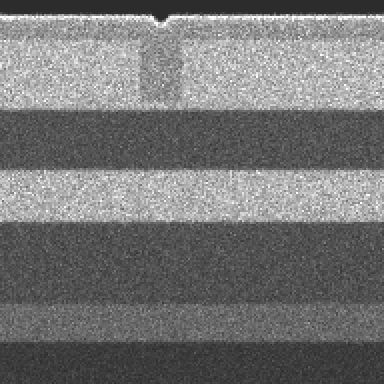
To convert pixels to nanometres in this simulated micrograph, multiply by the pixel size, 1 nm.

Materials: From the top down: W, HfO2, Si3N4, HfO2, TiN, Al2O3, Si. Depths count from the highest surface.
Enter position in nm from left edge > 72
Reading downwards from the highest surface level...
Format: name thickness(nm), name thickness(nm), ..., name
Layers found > W 24, HfO2 70, Si3N4 60, HfO2 52, TiN 82, Al2O3 38, Si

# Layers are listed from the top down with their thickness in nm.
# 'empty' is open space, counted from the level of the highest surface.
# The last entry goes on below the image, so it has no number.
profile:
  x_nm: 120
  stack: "W 24, HfO2 70, Si3N4 60, HfO2 52, TiN 82, Al2O3 38, Si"